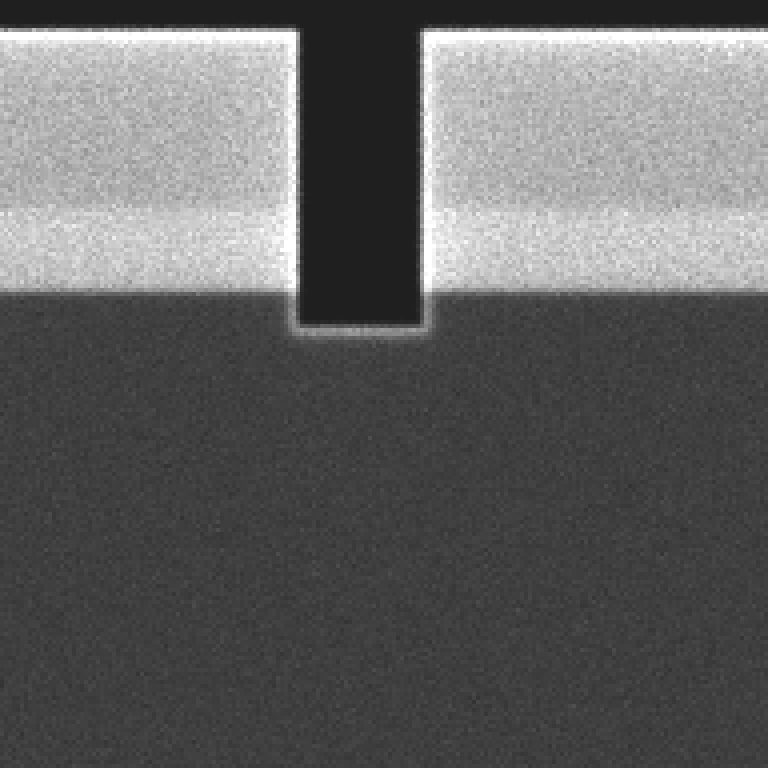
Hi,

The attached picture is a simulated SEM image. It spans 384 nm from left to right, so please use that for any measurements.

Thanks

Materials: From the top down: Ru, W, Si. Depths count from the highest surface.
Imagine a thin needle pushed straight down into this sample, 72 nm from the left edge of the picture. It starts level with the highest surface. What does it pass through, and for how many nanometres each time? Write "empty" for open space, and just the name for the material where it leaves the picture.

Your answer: Ru 88, W 42, Si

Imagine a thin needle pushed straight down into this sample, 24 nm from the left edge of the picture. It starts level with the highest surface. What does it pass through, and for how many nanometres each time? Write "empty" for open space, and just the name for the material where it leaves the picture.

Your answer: Ru 88, W 42, Si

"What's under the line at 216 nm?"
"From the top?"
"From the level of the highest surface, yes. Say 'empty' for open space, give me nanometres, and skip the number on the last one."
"Ru 88, W 42, Si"